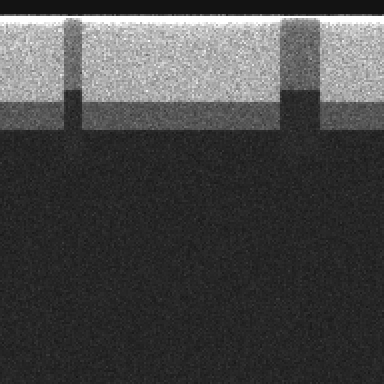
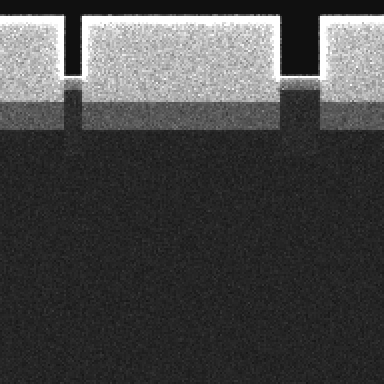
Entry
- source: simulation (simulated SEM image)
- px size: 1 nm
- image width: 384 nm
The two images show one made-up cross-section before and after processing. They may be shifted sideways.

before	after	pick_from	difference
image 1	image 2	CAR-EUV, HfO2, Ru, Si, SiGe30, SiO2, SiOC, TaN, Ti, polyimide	Ru removed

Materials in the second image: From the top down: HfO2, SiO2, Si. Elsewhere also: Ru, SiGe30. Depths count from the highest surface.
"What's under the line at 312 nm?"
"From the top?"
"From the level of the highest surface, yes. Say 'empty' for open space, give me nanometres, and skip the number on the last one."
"empty 60, Ru 14, SiGe30 66, Si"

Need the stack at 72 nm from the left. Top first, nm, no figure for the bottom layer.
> empty 60, Ru 14, SiGe30 66, Si